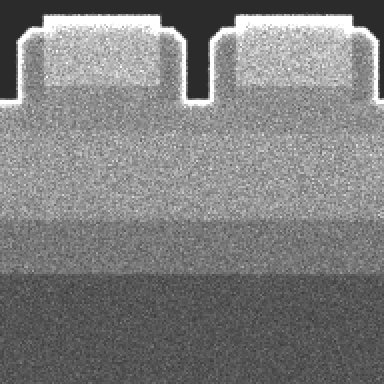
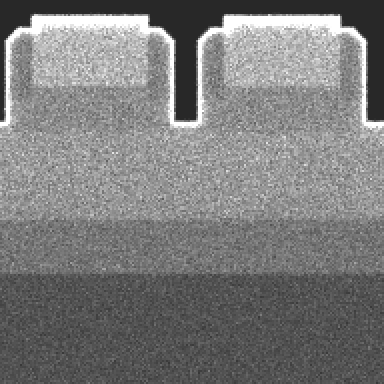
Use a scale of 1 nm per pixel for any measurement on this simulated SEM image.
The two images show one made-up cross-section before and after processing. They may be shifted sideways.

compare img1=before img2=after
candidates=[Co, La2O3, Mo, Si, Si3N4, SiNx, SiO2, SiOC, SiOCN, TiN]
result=removed:Si3N4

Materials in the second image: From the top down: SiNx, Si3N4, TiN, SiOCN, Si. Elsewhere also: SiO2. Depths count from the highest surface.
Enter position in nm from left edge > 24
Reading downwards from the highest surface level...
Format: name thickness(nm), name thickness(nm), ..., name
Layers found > empty 12, SiNx 72, Si3N4 32, TiN 88, SiOCN 54, Si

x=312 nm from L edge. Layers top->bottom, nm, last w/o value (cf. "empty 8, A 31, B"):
SiO2 70, Si3N4 46, TiN 88, SiOCN 54, Si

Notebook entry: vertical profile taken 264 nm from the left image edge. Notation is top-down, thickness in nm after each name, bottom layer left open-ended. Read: SiO2 70, Si3N4 46, TiN 88, SiOCN 54, Si